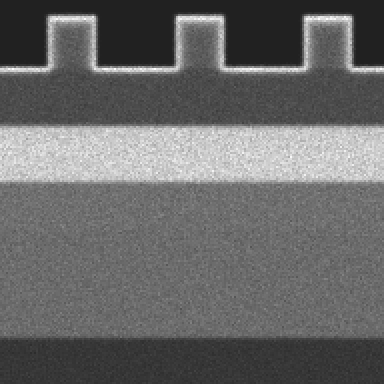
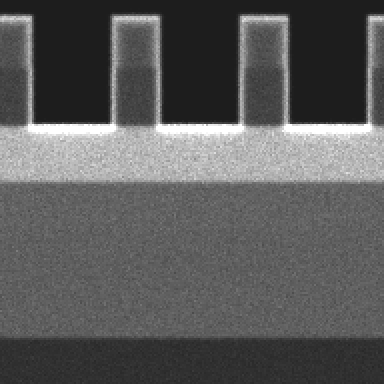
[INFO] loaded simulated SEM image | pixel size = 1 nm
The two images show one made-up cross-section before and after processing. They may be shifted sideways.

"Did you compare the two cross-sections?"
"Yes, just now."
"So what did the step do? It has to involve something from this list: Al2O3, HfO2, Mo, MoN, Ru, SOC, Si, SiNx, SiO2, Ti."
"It removed SiNx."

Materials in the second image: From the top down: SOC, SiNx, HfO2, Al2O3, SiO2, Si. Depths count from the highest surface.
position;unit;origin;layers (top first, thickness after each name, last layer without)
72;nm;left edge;empty 110, HfO2 56, Al2O3 48, SiO2 108, Si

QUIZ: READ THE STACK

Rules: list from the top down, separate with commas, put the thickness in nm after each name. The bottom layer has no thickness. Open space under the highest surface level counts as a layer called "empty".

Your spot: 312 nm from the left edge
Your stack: empty 110, HfO2 56, Al2O3 48, SiO2 108, Si